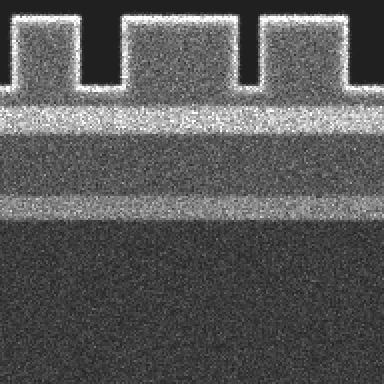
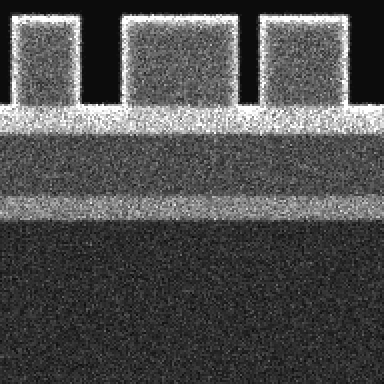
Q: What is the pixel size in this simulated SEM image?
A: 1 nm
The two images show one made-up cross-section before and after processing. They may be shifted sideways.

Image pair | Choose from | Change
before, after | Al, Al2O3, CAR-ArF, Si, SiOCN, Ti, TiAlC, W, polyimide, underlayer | underlayer (removed)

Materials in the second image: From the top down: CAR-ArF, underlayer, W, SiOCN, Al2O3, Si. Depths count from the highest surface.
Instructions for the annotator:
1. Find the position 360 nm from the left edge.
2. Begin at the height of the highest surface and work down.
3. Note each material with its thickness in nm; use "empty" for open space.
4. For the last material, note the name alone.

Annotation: empty 90, W 28, SiOCN 62, Al2O3 24, Si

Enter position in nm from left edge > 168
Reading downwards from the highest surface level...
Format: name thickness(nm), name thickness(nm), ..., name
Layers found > CAR-ArF 70, underlayer 20, W 28, SiOCN 62, Al2O3 24, Si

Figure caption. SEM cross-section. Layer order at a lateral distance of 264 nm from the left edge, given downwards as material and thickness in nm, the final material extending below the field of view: CAR-ArF 70, underlayer 20, W 28, SiOCN 62, Al2O3 24, Si